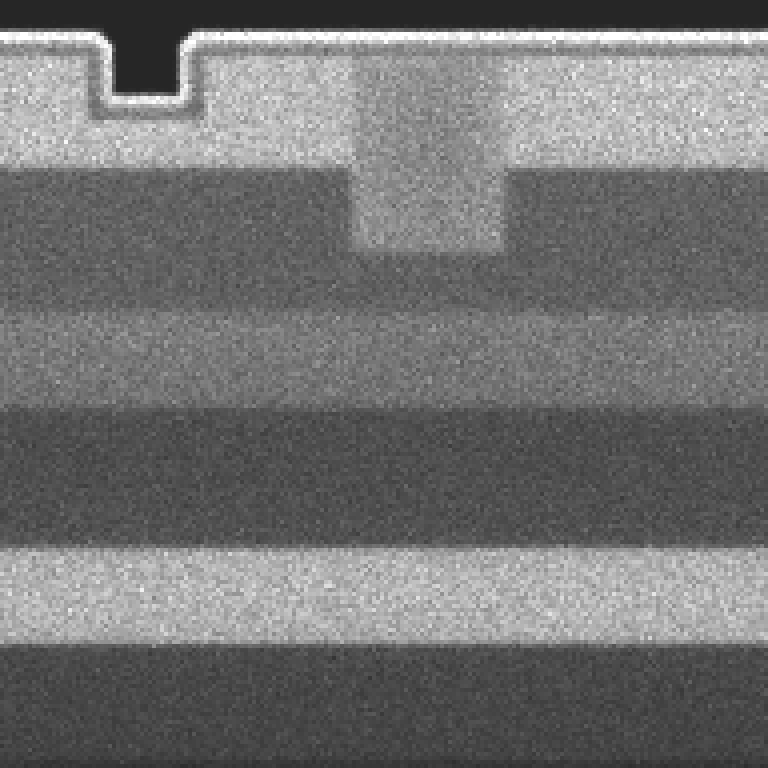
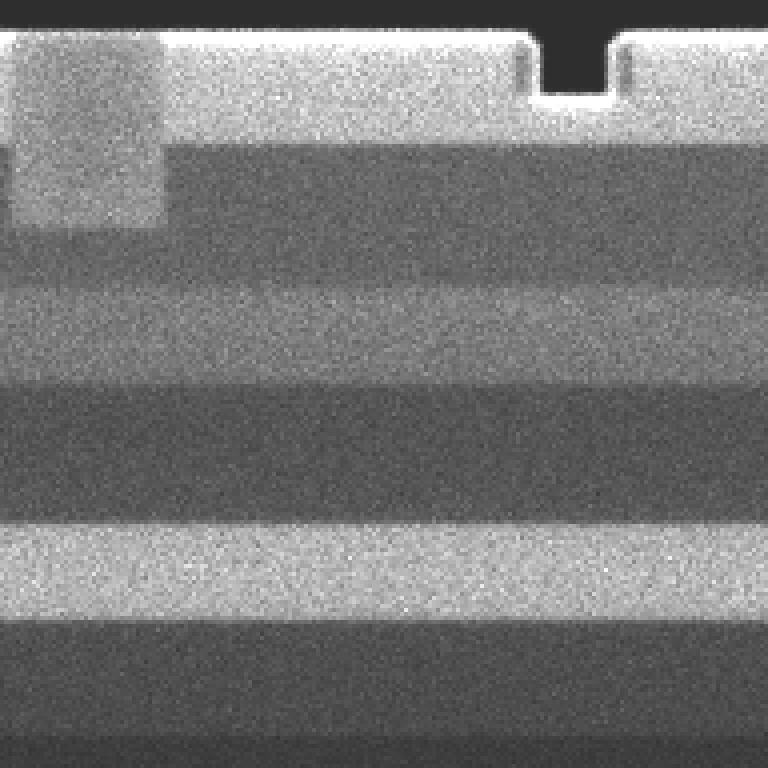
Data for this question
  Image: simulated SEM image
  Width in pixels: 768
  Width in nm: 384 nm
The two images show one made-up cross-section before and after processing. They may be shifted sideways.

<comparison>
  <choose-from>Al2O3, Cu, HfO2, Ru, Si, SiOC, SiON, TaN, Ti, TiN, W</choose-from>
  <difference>Al2O3 removed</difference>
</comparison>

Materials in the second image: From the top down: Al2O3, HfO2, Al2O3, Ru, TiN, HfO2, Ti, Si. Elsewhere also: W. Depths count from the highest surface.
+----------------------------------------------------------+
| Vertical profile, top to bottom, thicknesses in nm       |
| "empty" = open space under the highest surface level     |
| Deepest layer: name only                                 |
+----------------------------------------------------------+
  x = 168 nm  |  HfO2 56, Al2O3 72, Ru 48, TiN 70, HfO2 48, Ti 58, Si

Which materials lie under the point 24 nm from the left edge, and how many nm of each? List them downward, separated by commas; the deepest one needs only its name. W 98, Al2O3 30, Ru 48, TiN 70, HfO2 48, Ti 58, Si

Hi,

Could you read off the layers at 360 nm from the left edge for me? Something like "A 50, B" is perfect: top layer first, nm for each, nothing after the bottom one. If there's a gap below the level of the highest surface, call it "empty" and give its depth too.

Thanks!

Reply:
HfO2 56, Al2O3 72, Ru 48, TiN 70, HfO2 48, Ti 58, Si